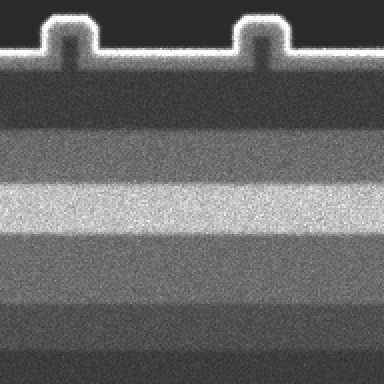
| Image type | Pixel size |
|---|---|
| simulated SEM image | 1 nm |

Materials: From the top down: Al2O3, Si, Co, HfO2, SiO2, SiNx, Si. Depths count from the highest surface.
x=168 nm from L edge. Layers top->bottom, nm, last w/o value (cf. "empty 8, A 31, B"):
empty 34, Al2O3 20, Si 60, Co 54, HfO2 50, SiO2 70, SiNx 46, Si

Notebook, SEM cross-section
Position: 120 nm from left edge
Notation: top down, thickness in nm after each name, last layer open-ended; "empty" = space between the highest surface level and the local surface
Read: empty 34, Al2O3 20, Si 60, Co 54, HfO2 50, SiO2 70, SiNx 46, Si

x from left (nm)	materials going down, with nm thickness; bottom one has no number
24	empty 34, Al2O3 20, Si 60, Co 54, HfO2 50, SiO2 70, SiNx 46, Si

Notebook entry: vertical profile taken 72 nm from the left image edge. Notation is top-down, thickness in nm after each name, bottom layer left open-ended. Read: Al2O3 20, Si 94, Co 54, HfO2 50, SiO2 70, SiNx 46, Si